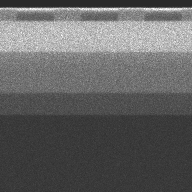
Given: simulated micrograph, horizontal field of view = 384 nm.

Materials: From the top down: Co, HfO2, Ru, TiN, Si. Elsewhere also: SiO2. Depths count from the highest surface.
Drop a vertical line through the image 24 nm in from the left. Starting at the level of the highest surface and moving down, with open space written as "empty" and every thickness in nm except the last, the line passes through Co 26, HfO2 62, Ru 82, TiN 44, Si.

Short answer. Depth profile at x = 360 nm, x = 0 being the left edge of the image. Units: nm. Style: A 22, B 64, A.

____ SiO2 26, HfO2 62, Ru 82, TiN 44, Si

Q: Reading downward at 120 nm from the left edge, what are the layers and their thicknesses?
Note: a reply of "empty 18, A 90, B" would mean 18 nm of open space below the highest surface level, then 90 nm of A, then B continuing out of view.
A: Co 26, HfO2 62, Ru 82, TiN 44, Si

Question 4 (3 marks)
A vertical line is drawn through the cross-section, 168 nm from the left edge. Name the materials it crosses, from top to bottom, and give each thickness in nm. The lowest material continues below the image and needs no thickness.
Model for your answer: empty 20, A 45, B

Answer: SiO2 26, HfO2 62, Ru 82, TiN 44, Si